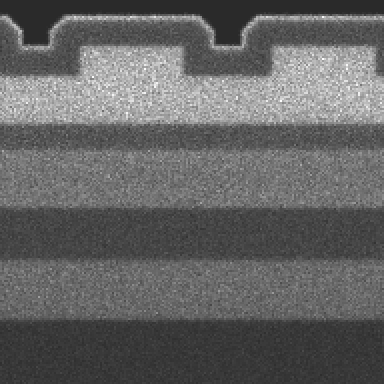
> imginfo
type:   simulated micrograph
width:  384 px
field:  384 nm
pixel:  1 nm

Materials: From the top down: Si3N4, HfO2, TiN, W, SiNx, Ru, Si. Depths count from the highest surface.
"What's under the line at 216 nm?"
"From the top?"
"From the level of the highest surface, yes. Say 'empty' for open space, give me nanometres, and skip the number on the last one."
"empty 30, Si3N4 30, HfO2 48, TiN 26, W 58, SiNx 52, Ru 60, Si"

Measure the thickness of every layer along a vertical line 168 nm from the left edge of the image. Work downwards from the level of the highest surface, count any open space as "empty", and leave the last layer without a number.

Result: Si3N4 30, HfO2 78, TiN 26, W 58, SiNx 52, Ru 60, Si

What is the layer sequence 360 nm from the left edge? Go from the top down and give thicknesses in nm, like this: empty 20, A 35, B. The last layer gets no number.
Si3N4 30, HfO2 78, TiN 26, W 58, SiNx 52, Ru 60, Si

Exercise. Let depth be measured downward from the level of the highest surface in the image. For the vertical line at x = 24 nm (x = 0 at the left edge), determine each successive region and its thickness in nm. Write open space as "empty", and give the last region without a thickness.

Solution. empty 30, Si3N4 30, HfO2 48, TiN 26, W 58, SiNx 52, Ru 60, Si